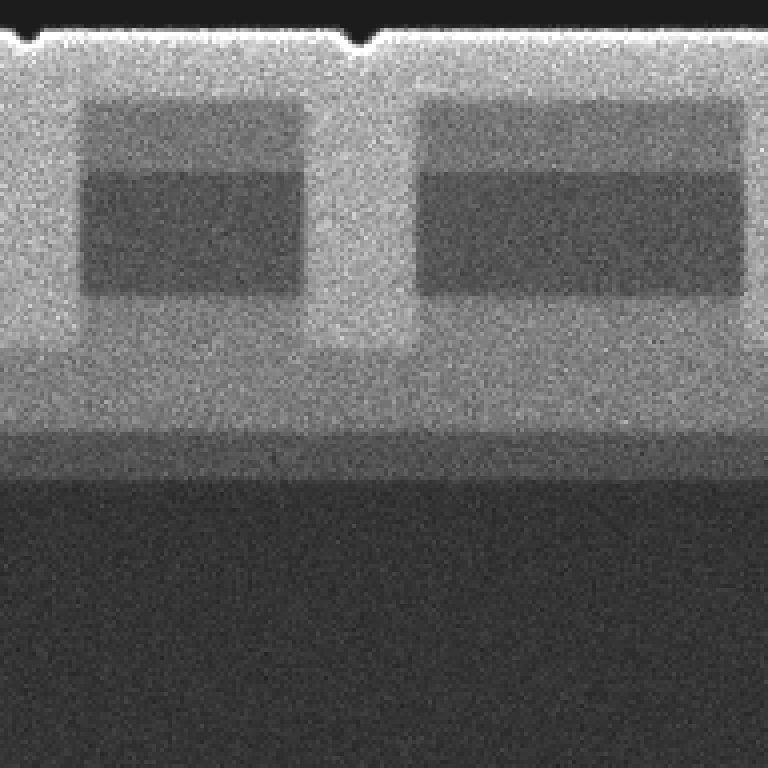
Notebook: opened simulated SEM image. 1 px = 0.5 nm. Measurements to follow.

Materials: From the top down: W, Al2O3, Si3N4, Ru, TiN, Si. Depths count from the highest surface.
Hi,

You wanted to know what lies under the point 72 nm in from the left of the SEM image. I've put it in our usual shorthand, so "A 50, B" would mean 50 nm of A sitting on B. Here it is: W 34, Al2O3 36, Si3N4 62, Ru 68, TiN 24, Si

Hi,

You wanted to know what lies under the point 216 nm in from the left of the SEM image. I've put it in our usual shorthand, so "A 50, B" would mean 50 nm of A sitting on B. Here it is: W 34, Al2O3 36, Si3N4 62, Ru 68, TiN 24, Si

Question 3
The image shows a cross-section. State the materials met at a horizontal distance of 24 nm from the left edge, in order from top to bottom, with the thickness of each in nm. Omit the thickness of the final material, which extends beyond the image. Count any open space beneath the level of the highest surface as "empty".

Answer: W 158, Ru 42, TiN 24, Si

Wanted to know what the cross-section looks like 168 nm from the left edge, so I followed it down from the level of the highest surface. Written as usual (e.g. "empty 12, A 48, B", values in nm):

W 158, Ru 42, TiN 24, Si